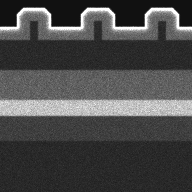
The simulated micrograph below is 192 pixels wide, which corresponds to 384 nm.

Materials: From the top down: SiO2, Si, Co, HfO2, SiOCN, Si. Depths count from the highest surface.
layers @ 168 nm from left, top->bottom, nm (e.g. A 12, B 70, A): empty 6, SiO2 58, Si 60, Co 60, HfO2 32, SiOCN 50, Si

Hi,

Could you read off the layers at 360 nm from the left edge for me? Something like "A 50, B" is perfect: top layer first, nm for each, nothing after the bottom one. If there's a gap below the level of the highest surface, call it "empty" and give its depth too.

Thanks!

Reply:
empty 38, SiO2 26, Si 60, Co 60, HfO2 32, SiOCN 50, Si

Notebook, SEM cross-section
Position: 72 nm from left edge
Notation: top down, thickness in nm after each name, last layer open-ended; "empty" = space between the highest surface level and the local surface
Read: SiO2 26, Si 98, Co 60, HfO2 32, SiOCN 50, Si